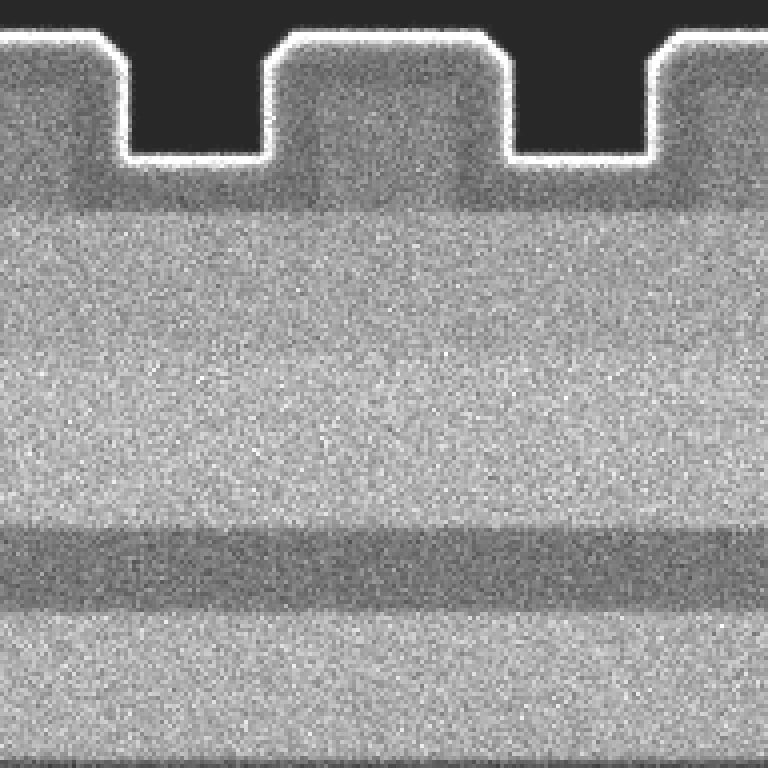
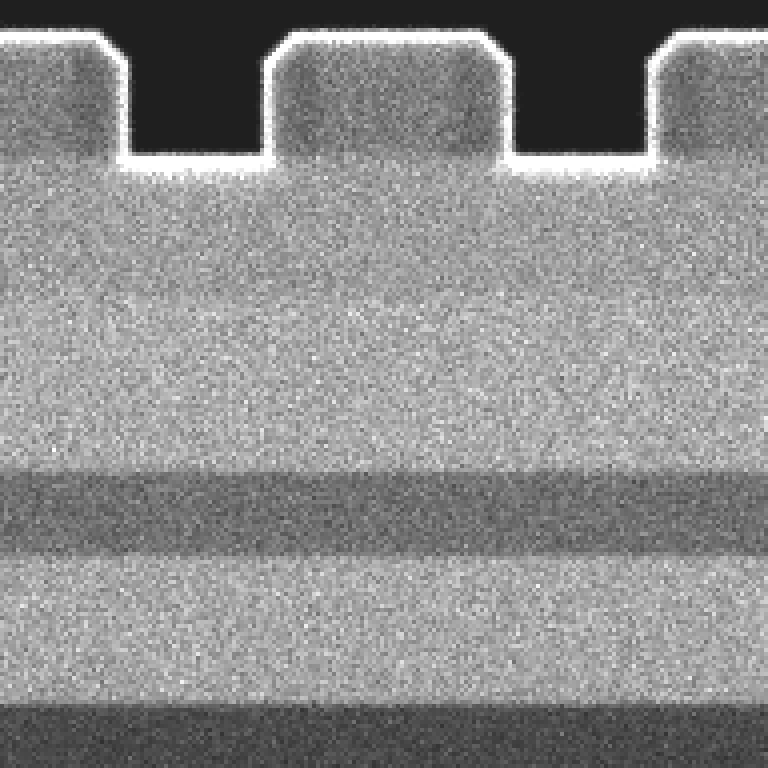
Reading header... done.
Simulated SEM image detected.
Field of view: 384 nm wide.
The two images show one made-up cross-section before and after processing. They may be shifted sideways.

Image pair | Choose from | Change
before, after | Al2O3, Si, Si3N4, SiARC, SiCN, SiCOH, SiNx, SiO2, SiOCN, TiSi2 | SiOCN (removed)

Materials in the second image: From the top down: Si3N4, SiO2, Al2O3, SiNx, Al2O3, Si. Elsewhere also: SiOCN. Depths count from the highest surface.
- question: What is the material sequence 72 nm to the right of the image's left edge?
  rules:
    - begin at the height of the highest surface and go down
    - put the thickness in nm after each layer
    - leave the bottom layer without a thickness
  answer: empty 62, SiO2 70, Al2O3 88, SiNx 42, Al2O3 74, Si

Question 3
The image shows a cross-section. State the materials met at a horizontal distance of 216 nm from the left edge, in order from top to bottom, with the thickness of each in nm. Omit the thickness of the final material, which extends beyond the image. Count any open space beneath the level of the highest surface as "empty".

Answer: Si3N4 62, SiO2 70, Al2O3 88, SiNx 42, Al2O3 74, Si